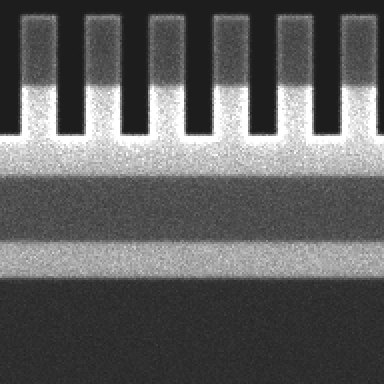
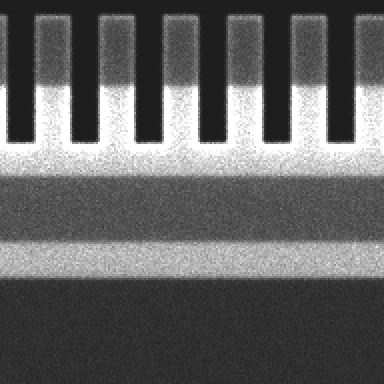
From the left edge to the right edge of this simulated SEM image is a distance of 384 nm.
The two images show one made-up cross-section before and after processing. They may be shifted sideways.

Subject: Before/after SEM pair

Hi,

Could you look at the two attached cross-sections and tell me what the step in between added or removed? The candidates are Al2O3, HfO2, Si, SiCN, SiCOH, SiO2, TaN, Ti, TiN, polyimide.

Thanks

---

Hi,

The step removed HfO2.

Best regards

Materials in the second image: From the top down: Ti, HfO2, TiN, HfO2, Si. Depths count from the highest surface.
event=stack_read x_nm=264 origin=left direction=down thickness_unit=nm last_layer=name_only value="empty 128, HfO2 32, TiN 66, HfO2 36, Si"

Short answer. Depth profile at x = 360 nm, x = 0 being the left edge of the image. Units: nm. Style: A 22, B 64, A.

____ Ti 70, HfO2 90, TiN 66, HfO2 36, Si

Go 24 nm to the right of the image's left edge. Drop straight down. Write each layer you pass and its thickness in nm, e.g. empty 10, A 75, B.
empty 128, HfO2 32, TiN 66, HfO2 36, Si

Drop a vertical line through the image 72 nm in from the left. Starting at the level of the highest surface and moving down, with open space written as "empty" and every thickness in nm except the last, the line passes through empty 128, HfO2 32, TiN 66, HfO2 36, Si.